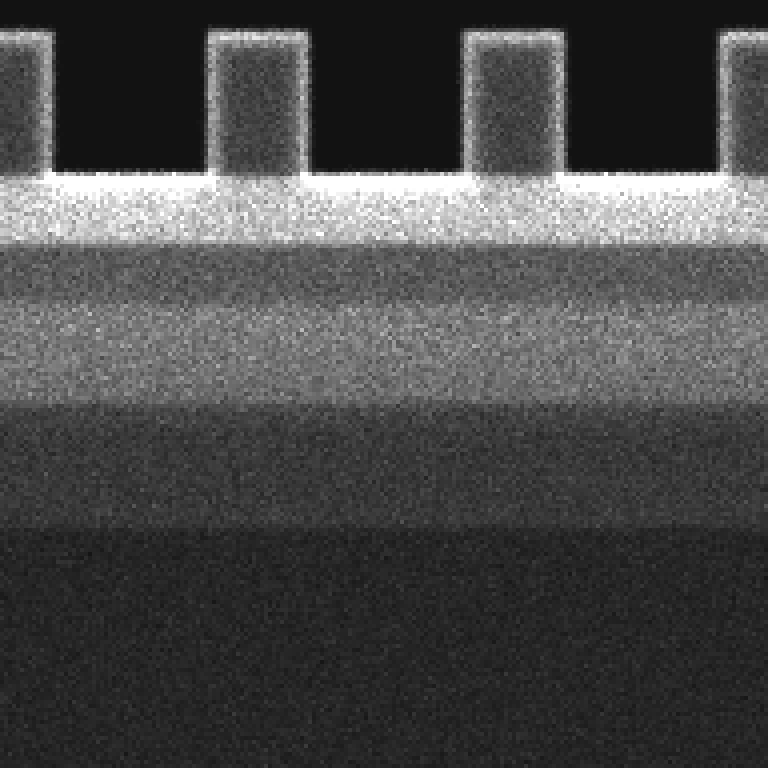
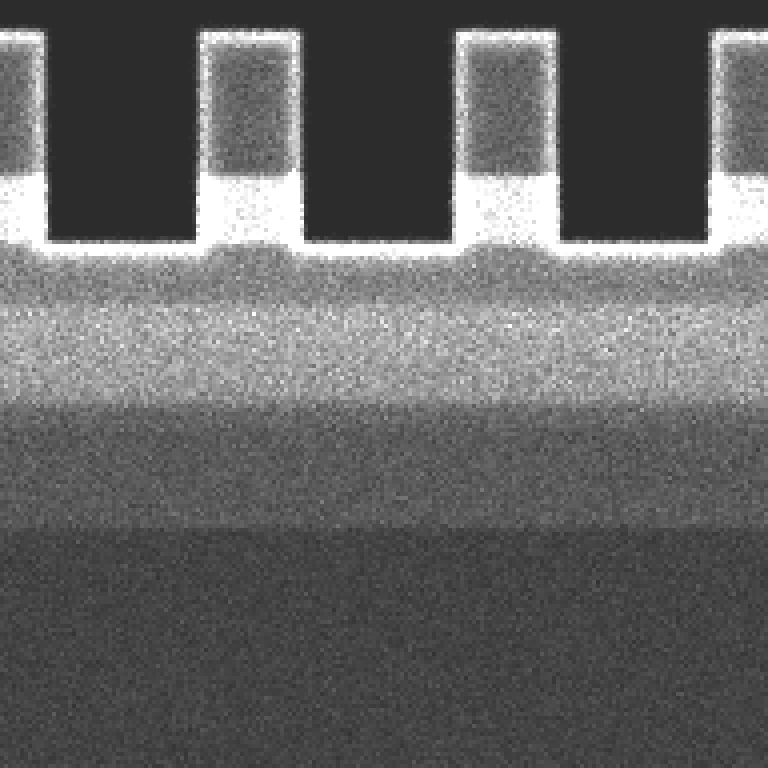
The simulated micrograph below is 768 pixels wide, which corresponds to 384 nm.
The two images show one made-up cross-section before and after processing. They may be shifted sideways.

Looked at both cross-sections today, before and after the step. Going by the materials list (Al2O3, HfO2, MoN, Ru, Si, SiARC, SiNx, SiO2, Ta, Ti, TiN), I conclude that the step removed HfO2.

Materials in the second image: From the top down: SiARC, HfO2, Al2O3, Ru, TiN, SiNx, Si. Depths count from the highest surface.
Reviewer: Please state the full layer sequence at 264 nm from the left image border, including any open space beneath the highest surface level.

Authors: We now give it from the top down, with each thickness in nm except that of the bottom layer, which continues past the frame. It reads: SiARC 72, HfO2 34, Al2O3 30, Ru 50, TiN 12, SiNx 50, Si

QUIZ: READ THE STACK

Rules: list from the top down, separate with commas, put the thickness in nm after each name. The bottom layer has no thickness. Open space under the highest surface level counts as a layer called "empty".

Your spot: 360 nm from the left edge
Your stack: SiARC 72, HfO2 34, Al2O3 30, Ru 50, TiN 12, SiNx 50, Si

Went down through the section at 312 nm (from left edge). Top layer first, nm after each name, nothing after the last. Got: empty 106, Al2O3 30, Ru 50, TiN 12, SiNx 50, Si